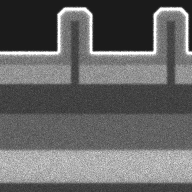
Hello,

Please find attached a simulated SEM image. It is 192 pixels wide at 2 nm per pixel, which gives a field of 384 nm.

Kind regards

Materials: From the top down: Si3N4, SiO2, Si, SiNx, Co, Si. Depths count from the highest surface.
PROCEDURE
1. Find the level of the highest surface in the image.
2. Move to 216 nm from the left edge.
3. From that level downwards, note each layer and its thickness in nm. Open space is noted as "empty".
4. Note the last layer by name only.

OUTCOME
empty 88, Si3N4 26, SiO2 38, Si 60, SiNx 72, Co 66, Si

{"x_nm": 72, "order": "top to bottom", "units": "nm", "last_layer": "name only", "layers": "empty 88, Si3N4 26, SiO2 38, Si 60, SiNx 72, Co 66, Si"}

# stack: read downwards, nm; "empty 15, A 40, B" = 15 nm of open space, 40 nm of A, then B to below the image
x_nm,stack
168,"Si3N4 114, SiO2 38, Si 60, SiNx 72, Co 66, Si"